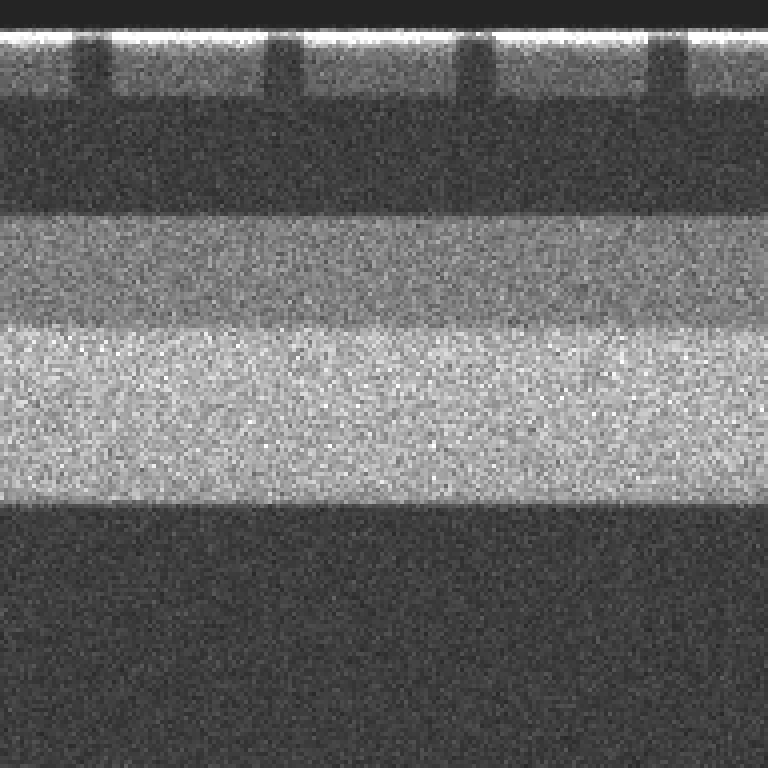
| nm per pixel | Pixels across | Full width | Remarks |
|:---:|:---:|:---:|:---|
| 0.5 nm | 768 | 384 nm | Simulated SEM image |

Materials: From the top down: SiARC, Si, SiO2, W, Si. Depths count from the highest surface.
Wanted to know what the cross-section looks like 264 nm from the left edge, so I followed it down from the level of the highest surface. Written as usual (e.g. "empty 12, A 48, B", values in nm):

SiARC 32, Si 60, SiO2 56, W 88, Si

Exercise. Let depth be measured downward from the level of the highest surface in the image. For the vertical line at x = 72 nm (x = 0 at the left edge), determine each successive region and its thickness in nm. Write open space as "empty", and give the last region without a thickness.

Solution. SiARC 32, Si 60, SiO2 56, W 88, Si